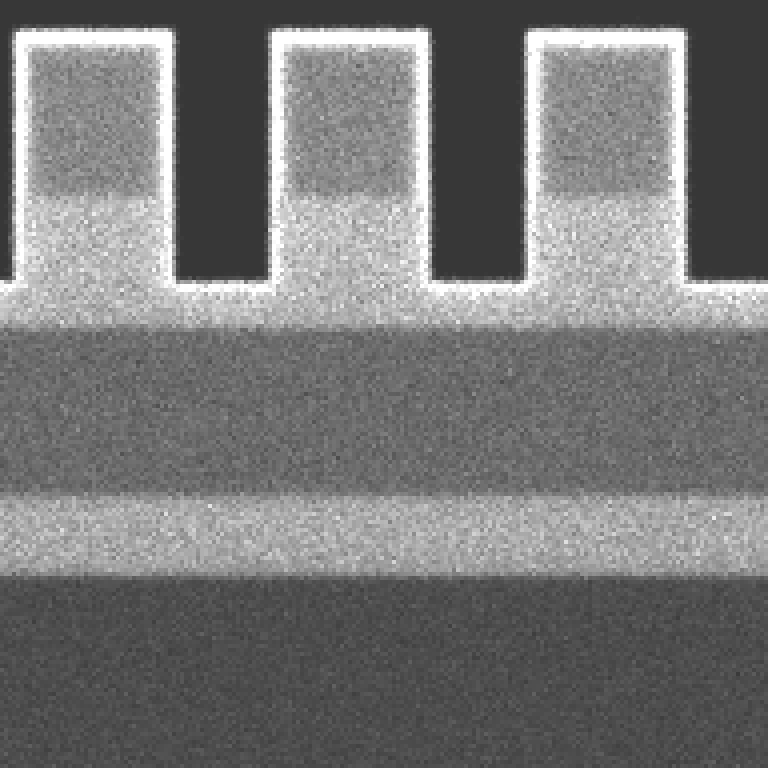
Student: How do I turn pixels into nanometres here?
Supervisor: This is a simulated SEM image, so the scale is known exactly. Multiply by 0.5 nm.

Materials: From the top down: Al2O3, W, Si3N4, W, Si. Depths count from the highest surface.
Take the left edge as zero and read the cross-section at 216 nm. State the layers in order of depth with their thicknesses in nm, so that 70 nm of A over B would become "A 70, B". empty 126, W 22, Si3N4 84, W 40, Si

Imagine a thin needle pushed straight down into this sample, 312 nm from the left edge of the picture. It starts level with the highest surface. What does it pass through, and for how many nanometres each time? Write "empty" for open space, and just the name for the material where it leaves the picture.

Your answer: Al2O3 82, W 66, Si3N4 84, W 40, Si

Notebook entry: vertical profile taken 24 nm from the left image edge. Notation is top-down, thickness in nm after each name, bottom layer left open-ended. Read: Al2O3 82, W 66, Si3N4 84, W 40, Si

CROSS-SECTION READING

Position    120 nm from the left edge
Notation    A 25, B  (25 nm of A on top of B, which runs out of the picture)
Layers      empty 126, W 22, Si3N4 84, W 40, Si